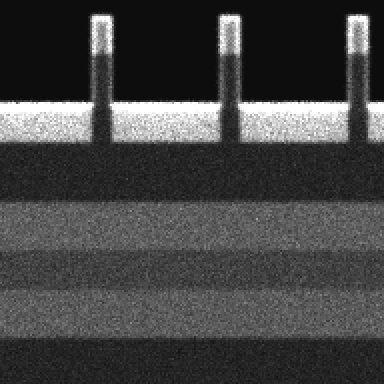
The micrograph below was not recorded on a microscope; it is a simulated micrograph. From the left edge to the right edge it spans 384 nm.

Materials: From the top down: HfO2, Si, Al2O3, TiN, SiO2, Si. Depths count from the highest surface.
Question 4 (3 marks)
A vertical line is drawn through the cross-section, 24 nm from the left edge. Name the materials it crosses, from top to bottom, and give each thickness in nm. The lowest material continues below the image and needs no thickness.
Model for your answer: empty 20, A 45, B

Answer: empty 88, HfO2 38, Si 60, Al2O3 48, TiN 40, SiO2 48, Si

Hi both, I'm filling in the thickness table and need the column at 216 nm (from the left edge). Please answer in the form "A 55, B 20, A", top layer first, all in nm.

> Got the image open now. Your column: empty 88, HfO2 38, Si 60, Al2O3 48, TiN 40, SiO2 48, Si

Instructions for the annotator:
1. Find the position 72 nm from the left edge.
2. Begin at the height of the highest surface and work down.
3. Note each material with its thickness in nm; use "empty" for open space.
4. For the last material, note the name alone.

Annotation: empty 88, HfO2 38, Si 60, Al2O3 48, TiN 40, SiO2 48, Si